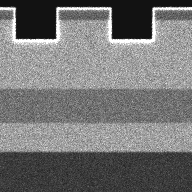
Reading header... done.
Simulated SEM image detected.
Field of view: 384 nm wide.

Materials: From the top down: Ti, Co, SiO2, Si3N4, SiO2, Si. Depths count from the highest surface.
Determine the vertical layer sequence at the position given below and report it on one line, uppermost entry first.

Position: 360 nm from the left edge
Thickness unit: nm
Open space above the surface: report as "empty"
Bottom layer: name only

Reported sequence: Ti 24, Co 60, SiO2 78, Si3N4 68, SiO2 58, Si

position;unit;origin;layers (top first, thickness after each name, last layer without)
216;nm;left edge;Ti 24, Co 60, SiO2 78, Si3N4 68, SiO2 58, Si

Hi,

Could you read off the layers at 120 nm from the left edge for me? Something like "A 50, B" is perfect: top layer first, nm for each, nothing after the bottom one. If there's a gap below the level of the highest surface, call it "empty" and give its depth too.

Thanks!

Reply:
Ti 24, Co 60, SiO2 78, Si3N4 68, SiO2 58, Si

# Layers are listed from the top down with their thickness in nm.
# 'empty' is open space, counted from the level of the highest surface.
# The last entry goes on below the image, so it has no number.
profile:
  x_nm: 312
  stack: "Ti 24, Co 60, SiO2 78, Si3N4 68, SiO2 58, Si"